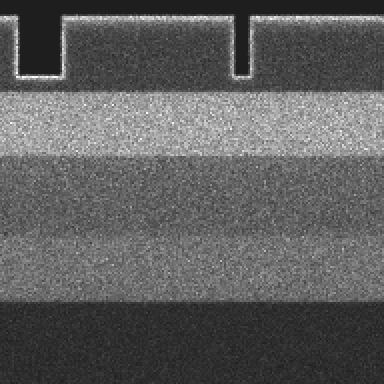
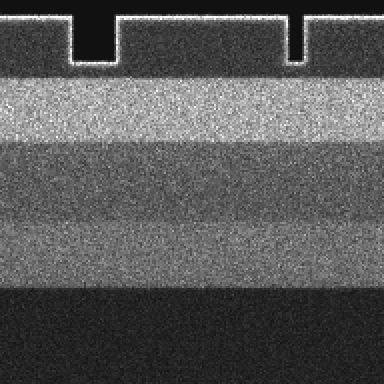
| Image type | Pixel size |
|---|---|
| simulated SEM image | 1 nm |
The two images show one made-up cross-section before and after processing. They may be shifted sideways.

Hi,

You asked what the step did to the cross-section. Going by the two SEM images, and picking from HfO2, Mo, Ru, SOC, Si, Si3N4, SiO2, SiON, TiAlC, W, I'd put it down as SOC, removed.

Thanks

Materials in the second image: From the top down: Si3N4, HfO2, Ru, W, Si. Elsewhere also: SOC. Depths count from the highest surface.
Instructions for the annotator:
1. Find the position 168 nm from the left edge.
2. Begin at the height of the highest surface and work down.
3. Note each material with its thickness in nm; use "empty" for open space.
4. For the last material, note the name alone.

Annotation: Si3N4 62, HfO2 64, Ru 80, W 66, Si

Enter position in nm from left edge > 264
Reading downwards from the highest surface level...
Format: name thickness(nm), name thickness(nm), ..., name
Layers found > Si3N4 62, HfO2 64, Ru 80, W 66, Si